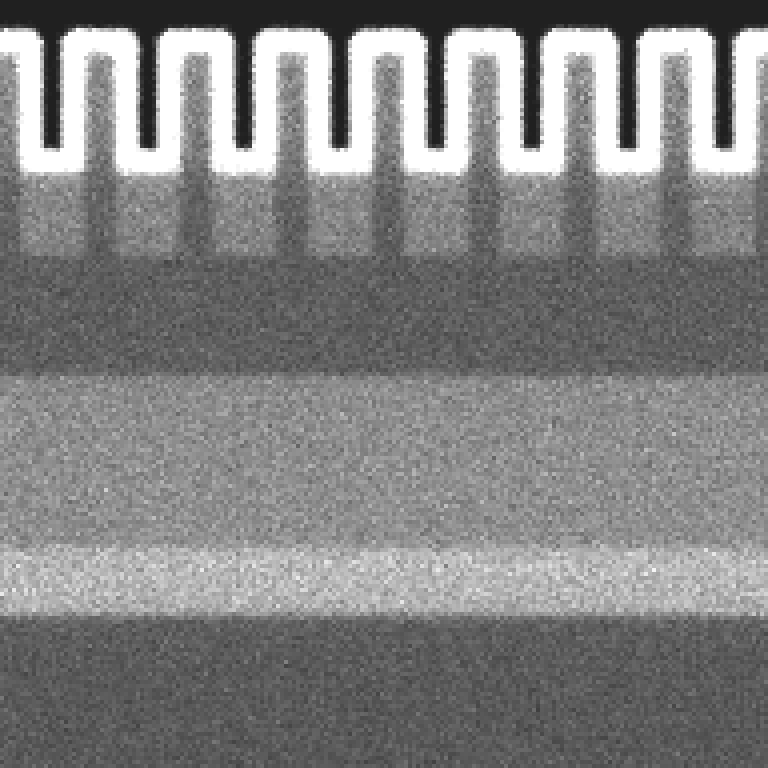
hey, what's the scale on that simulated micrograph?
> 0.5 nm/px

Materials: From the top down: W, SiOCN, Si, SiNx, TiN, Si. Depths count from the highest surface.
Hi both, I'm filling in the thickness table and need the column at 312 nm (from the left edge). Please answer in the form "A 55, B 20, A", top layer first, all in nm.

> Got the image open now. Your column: empty 60, W 10, SiOCN 42, Si 60, SiNx 86, TiN 34, Si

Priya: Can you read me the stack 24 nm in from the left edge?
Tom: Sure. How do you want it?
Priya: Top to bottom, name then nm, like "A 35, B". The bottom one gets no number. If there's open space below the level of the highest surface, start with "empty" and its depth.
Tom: empty 60, W 10, SiOCN 42, Si 60, SiNx 86, TiN 34, Si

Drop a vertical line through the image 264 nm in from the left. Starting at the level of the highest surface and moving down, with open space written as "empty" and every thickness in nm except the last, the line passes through empty 60, W 10, SiOCN 42, Si 60, SiNx 86, TiN 34, Si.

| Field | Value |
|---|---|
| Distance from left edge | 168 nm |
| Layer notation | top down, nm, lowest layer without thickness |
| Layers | empty 60, W 10, SiOCN 42, Si 60, SiNx 86, TiN 34, Si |